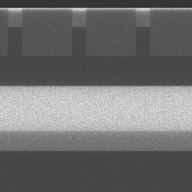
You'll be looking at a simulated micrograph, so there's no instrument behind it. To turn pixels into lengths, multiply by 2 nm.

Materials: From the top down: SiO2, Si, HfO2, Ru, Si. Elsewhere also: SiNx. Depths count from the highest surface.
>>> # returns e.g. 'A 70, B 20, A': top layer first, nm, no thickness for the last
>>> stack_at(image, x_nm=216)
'SiNx 96, Si 60, HfO2 90, Ru 40, Si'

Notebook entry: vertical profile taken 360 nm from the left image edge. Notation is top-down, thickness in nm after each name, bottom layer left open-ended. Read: SiNx 96, Si 60, HfO2 90, Ru 40, Si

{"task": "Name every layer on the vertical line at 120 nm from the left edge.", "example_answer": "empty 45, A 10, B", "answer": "SiNx 96, Si 60, HfO2 90, Ru 40, Si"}